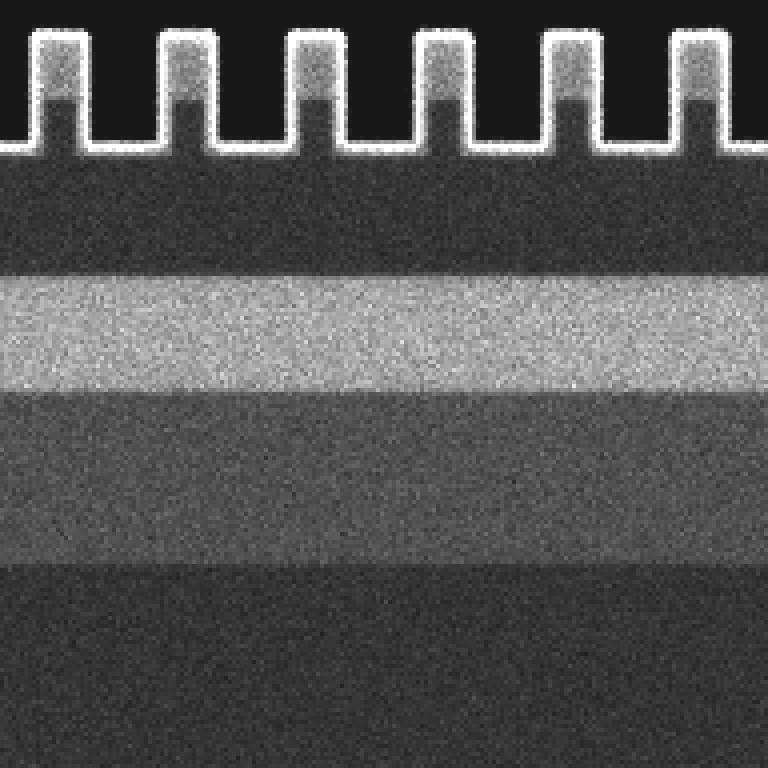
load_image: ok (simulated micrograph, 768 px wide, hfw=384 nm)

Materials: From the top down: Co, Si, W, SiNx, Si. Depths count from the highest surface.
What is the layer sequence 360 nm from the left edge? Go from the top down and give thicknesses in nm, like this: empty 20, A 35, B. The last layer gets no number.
Co 62, Si 60, W 58, SiNx 86, Si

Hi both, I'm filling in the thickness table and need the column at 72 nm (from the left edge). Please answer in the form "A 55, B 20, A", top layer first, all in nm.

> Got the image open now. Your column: empty 56, Co 6, Si 60, W 58, SiNx 86, Si